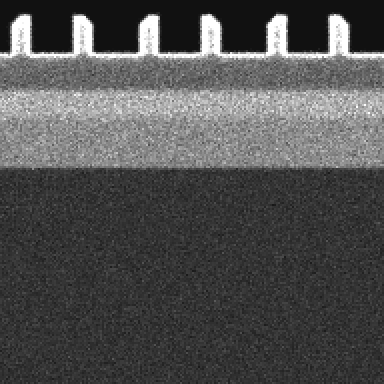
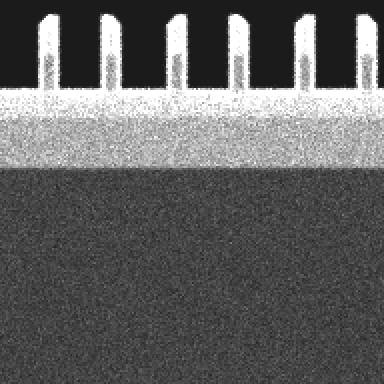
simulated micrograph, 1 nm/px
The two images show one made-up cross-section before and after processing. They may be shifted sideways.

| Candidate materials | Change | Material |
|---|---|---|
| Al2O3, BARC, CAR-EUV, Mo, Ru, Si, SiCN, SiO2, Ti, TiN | removed | TiN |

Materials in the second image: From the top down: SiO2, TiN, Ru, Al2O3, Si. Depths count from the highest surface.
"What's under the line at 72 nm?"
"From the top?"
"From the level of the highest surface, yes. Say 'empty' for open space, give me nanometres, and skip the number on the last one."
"empty 74, Ru 28, Al2O3 50, Si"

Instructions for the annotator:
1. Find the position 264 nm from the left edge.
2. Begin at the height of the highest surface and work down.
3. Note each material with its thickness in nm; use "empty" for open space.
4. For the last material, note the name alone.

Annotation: empty 74, Ru 28, Al2O3 50, Si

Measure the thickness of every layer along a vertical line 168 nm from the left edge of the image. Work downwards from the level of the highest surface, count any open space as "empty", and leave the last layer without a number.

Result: empty 8, SiO2 30, TiN 36, Ru 28, Al2O3 50, Si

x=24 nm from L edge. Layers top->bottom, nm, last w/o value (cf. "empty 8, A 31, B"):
empty 74, Ru 28, Al2O3 50, Si